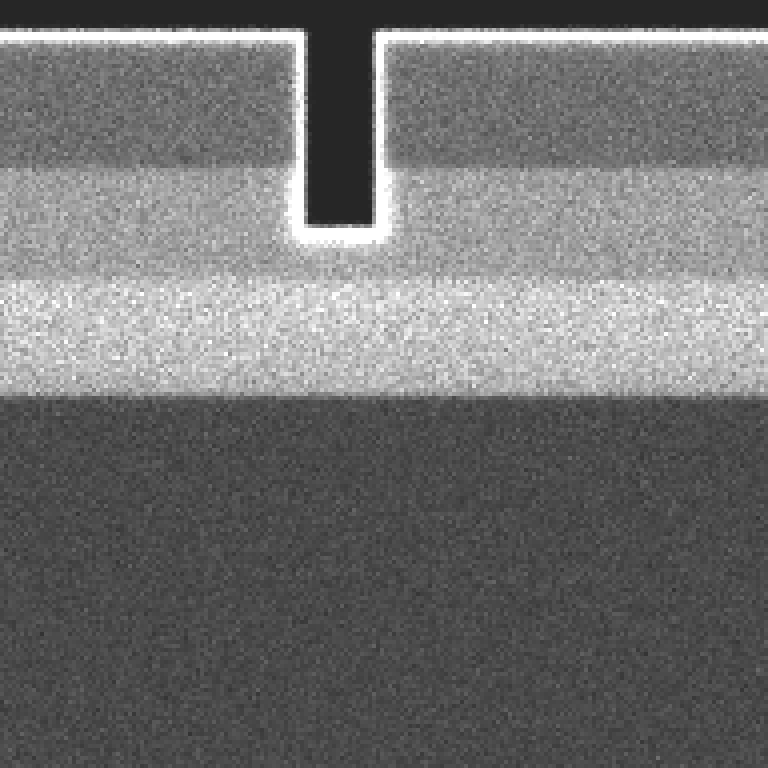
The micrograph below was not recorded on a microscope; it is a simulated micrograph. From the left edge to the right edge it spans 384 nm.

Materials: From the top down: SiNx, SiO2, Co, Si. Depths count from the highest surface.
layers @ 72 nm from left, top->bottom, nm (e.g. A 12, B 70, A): SiNx 68, SiO2 56, Co 58, Si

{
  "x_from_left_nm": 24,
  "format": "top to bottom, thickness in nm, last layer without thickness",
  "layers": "SiNx 68, SiO2 56, Co 58, Si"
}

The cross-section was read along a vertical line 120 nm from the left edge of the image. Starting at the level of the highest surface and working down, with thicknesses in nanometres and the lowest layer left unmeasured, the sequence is SiNx 68, SiO2 56, Co 58, Si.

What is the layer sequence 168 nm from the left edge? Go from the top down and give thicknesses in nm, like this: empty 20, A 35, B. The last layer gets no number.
empty 98, SiO2 26, Co 58, Si